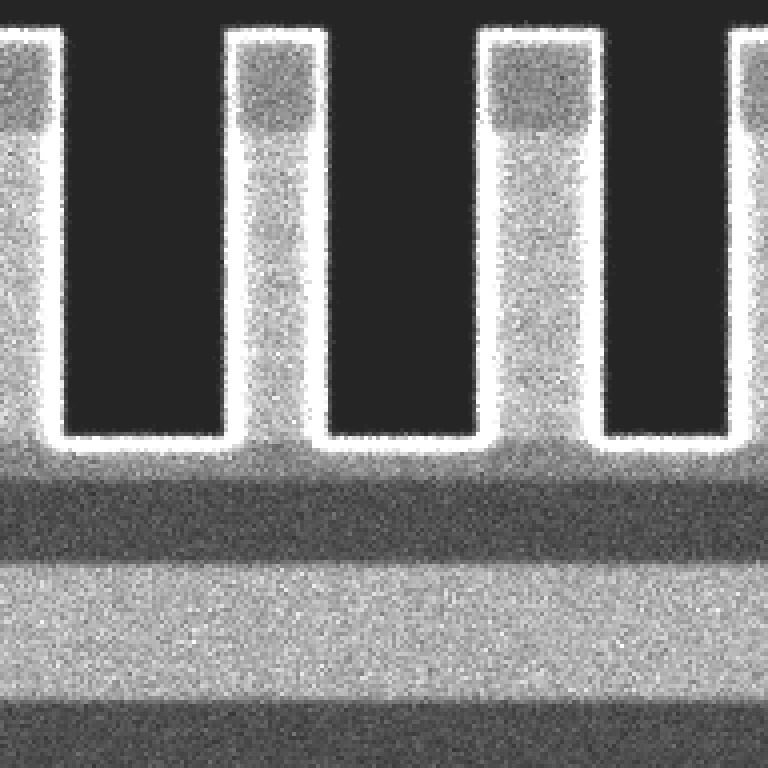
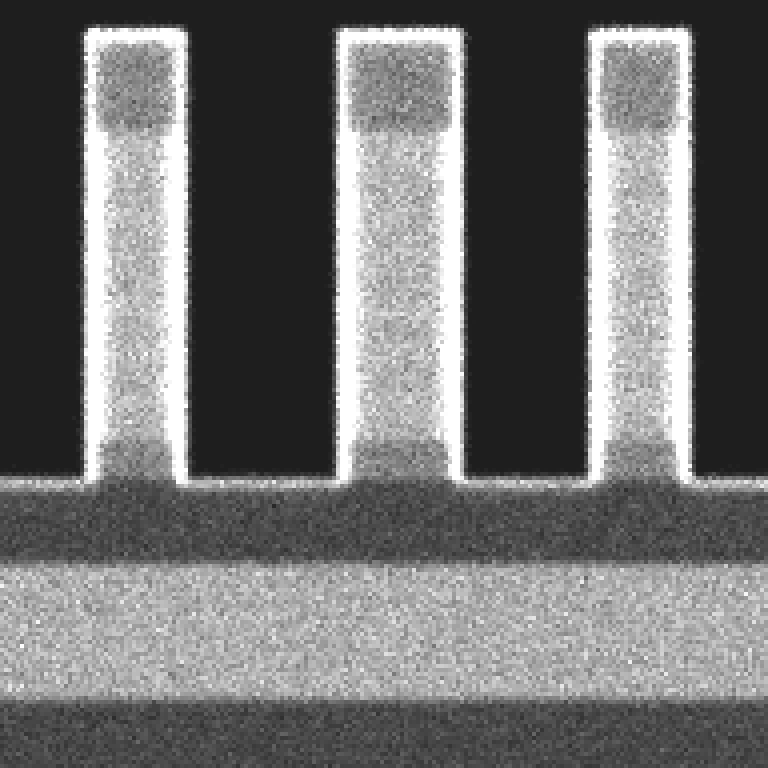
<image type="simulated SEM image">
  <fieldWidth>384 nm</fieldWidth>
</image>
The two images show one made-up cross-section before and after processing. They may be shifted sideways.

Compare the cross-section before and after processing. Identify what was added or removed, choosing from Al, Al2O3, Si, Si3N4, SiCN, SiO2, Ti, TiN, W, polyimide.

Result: Si3N4 removed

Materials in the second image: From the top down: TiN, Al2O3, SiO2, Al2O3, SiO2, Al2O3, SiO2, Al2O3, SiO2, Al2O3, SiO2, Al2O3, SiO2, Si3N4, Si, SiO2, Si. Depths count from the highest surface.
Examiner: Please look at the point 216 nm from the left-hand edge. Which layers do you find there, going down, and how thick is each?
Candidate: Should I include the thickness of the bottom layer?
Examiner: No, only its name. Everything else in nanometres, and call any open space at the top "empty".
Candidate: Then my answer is TiN 50, Al2O3 22, SiO2 12, Al2O3 12, SiO2 12, Al2O3 12, SiO2 12, Al2O3 12, SiO2 12, Al2O3 12, SiO2 12, Al2O3 12, SiO2 12, Si3N4 20, Si 42, SiO2 68, Si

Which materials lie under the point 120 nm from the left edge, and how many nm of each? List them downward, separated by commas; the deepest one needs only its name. empty 224, Si 42, SiO2 68, Si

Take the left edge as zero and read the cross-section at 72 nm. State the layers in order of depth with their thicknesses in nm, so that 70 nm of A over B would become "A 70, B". TiN 50, Al2O3 22, SiO2 12, Al2O3 12, SiO2 12, Al2O3 12, SiO2 12, Al2O3 12, SiO2 12, Al2O3 12, SiO2 12, Al2O3 12, SiO2 12, Si3N4 20, Si 42, SiO2 68, Si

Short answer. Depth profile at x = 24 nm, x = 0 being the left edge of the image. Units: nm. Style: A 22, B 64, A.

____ empty 224, Si 42, SiO2 68, Si